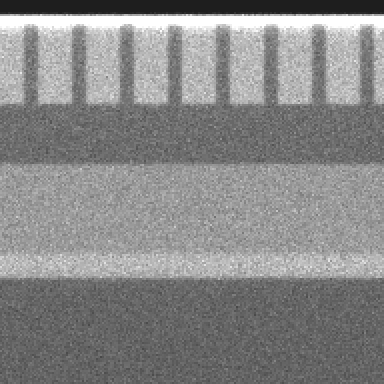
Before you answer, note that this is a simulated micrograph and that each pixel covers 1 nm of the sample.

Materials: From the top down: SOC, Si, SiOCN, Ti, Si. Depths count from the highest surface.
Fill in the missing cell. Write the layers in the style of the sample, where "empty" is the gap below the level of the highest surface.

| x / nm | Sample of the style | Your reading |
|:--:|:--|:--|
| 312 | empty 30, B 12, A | SOC 6, Si 142, SiOCN 90, Ti 24, Si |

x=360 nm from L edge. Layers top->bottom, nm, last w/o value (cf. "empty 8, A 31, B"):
SOC 6, Si 142, SiOCN 90, Ti 24, Si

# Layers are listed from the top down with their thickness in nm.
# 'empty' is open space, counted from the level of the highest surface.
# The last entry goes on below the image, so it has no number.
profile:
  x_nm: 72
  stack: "SOC 6, Si 142, SiOCN 90, Ti 24, Si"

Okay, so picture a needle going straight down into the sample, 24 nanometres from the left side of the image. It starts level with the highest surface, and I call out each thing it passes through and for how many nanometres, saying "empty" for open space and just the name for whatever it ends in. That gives SOC 6, Si 142, SiOCN 90, Ti 24, Si